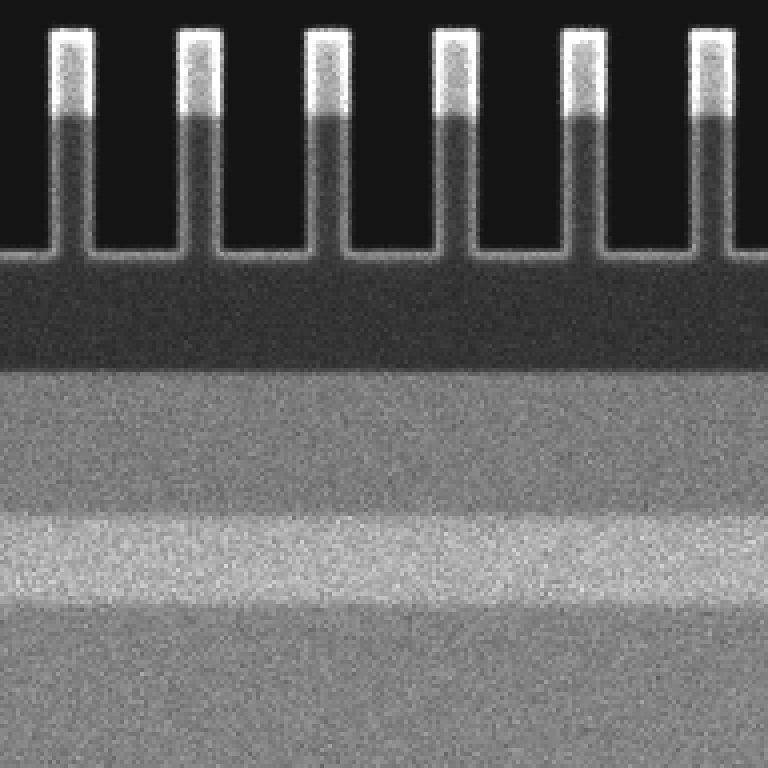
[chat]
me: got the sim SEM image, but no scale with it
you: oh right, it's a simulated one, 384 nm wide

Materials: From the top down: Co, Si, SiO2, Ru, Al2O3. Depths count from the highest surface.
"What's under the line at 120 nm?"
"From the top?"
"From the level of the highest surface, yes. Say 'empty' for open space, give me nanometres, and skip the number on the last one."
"empty 110, Si 60, SiO2 72, Ru 44, Al2O3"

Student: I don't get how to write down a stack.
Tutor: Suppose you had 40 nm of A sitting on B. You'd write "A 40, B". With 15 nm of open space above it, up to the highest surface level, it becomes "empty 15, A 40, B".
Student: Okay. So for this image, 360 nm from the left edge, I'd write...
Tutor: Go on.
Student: Co 42, Si 128, SiO2 72, Ru 44, Al2O3